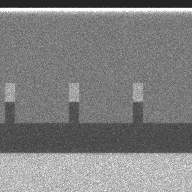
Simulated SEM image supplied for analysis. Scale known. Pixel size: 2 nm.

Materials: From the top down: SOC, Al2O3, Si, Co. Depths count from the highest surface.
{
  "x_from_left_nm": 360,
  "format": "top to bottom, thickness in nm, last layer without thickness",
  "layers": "SOC 230, Si 60, Co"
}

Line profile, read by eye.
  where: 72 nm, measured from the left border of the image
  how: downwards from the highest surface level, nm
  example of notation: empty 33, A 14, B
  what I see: SOC 230, Si 60, Co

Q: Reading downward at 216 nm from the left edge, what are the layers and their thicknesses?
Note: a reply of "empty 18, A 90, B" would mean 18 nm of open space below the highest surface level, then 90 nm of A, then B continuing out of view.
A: SOC 230, Si 60, Co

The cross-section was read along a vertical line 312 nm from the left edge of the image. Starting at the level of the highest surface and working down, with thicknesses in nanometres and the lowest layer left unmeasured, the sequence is SOC 230, Si 60, Co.